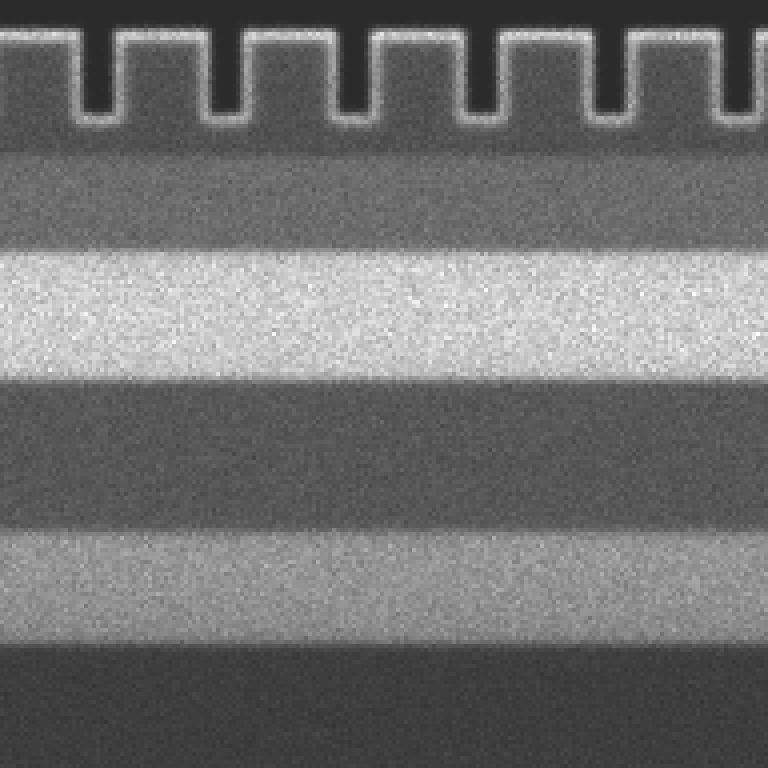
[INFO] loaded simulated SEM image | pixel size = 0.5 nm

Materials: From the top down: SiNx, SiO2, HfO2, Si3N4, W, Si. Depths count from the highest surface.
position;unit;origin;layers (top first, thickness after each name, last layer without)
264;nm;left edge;SiNx 62, SiO2 48, HfO2 64, Si3N4 76, W 56, Si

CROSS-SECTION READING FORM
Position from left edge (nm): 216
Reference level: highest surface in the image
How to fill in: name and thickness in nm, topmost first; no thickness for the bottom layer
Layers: SiNx 62, SiO2 48, HfO2 64, Si3N4 76, W 56, Si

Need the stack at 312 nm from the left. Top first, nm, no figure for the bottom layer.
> empty 42, SiNx 20, SiO2 48, HfO2 64, Si3N4 76, W 56, Si